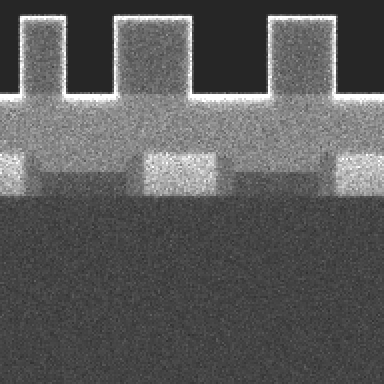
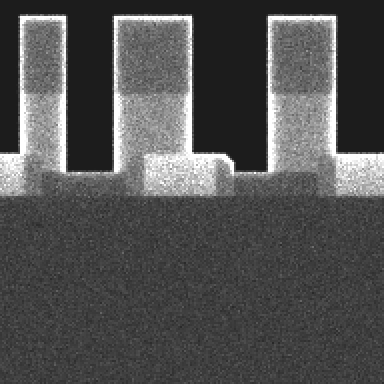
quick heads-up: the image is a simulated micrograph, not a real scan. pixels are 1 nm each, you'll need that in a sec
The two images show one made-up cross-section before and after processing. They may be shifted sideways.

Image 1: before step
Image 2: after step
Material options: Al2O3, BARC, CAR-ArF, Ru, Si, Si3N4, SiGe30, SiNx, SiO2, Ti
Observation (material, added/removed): SiO2, removed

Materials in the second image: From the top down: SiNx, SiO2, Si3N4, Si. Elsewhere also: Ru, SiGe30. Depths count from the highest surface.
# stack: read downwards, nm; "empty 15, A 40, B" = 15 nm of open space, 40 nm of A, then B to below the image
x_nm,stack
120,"SiNx 78, SiO2 78, SiGe30 24, Si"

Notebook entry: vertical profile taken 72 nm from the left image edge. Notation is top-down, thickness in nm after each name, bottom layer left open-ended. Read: empty 156, SiGe30 24, Si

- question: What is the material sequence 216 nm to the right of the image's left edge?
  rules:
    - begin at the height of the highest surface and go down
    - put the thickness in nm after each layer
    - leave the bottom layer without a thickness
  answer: empty 138, Si3N4 42, Si